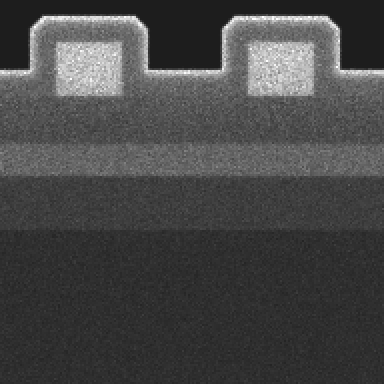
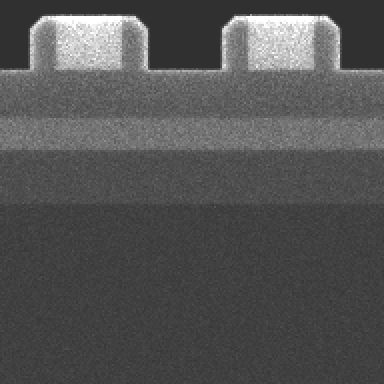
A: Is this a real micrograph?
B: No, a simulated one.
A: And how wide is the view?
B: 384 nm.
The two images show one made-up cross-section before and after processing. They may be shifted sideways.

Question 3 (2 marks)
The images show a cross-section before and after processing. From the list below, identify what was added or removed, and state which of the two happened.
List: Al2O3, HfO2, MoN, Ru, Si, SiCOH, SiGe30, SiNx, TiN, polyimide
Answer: Al2O3 was removed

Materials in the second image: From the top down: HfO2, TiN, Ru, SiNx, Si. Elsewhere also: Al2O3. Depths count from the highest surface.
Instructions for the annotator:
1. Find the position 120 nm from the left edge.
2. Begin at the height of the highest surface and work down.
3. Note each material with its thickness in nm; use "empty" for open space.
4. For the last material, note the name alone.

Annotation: HfO2 54, TiN 48, Ru 32, SiNx 54, Si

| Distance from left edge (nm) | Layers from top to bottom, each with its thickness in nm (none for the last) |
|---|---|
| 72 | HfO2 54, TiN 48, Ru 32, SiNx 54, Si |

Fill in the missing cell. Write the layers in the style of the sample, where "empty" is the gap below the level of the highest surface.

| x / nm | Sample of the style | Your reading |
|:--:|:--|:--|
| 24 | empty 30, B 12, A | empty 54, TiN 48, Ru 32, SiNx 54, Si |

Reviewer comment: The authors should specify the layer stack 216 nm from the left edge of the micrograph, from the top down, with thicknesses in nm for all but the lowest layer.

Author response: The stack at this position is empty 54, TiN 48, Ru 32, SiNx 54, Si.